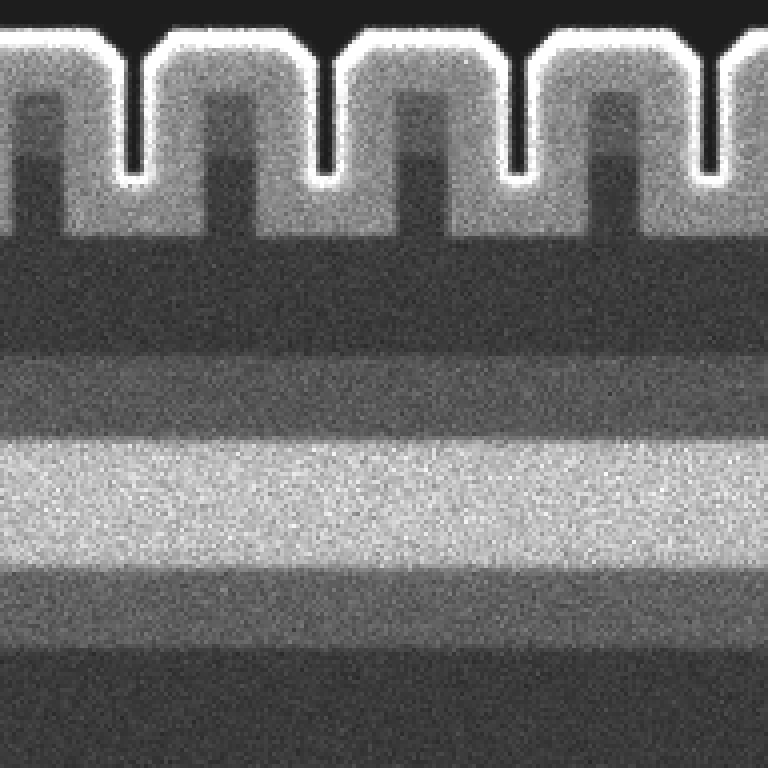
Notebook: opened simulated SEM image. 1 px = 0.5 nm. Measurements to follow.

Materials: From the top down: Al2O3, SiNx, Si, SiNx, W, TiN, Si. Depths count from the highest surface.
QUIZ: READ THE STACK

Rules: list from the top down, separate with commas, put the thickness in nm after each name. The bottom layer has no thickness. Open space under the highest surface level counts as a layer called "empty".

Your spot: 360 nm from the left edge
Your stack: empty 14, Al2O3 88, Si 60, SiNx 42, W 64, TiN 40, Si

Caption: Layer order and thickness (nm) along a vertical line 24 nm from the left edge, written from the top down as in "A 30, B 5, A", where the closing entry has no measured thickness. Al2O3 30, SiNx 32, Si 100, SiNx 42, W 64, TiN 40, Si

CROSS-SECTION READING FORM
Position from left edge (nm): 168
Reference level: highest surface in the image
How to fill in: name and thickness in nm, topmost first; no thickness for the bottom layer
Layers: empty 14, Al2O3 88, Si 60, SiNx 42, W 64, TiN 40, Si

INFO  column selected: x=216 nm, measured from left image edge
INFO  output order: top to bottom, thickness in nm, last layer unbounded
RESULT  Al2O3 30, SiNx 32, Si 100, SiNx 42, W 64, TiN 40, Si